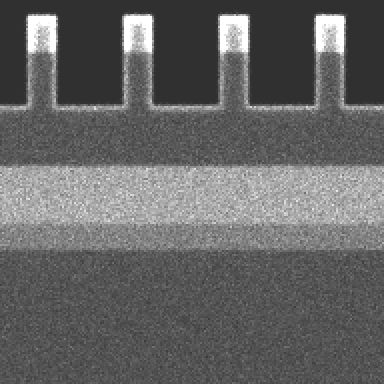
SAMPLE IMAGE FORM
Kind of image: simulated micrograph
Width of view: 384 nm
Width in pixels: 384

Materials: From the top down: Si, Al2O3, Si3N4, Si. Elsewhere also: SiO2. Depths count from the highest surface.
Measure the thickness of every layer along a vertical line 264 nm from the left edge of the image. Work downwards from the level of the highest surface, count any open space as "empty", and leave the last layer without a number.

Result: empty 90, Si 60, Al2O3 58, Si3N4 26, Si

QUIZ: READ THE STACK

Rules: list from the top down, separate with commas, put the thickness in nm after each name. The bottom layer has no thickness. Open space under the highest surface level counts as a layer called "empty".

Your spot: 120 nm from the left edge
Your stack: empty 90, Si 60, Al2O3 58, Si3N4 26, Si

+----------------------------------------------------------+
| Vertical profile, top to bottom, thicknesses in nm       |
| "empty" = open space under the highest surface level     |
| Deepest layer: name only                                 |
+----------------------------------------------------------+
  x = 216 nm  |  empty 90, Si 60, Al2O3 58, Si3N4 26, Si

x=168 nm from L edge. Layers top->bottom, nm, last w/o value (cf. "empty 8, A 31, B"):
empty 90, Si 60, Al2O3 58, Si3N4 26, Si